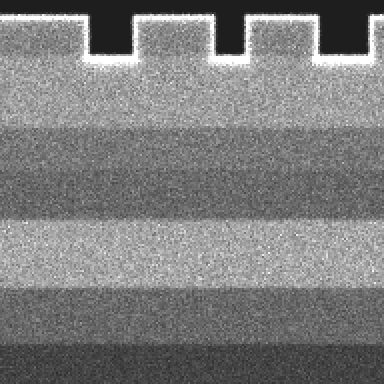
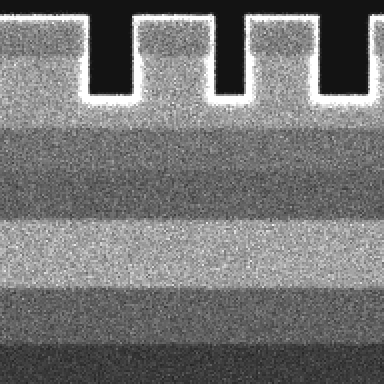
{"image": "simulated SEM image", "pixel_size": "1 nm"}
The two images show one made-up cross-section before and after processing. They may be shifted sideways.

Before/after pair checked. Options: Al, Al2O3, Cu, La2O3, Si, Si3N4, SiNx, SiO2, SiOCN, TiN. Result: removed SiO2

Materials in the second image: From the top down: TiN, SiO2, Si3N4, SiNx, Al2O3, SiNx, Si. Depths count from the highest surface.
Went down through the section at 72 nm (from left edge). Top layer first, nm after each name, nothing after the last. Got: TiN 40, SiO2 72, Si3N4 42, SiNx 50, Al2O3 68, SiNx 56, Si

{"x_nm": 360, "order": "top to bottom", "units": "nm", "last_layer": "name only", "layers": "empty 80, SiO2 32, Si3N4 42, SiNx 50, Al2O3 68, SiNx 56, Si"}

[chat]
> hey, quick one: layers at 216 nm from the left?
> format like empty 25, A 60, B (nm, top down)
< empty 80, SiO2 32, Si3N4 42, SiNx 50, Al2O3 68, SiNx 56, Si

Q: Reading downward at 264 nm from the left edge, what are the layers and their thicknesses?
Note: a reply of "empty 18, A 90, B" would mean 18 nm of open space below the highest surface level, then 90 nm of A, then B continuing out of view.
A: TiN 40, SiO2 72, Si3N4 42, SiNx 50, Al2O3 68, SiNx 56, Si